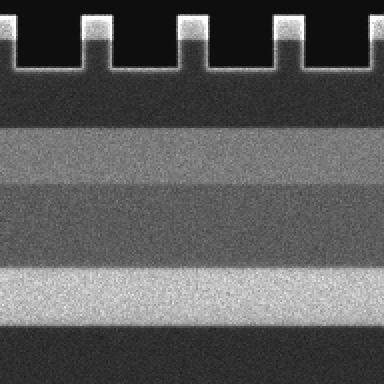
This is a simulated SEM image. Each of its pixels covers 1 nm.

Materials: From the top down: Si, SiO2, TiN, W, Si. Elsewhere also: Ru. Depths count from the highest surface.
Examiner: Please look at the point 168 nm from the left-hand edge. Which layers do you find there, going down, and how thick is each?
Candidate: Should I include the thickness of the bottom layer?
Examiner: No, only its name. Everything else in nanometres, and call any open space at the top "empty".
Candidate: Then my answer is empty 52, Si 60, SiO2 56, TiN 84, W 58, Si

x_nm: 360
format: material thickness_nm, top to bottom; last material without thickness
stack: empty 52, Si 60, SiO2 56, TiN 84, W 58, Si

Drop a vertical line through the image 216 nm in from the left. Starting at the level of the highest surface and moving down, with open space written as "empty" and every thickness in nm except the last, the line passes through empty 52, Si 60, SiO2 56, TiN 84, W 58, Si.